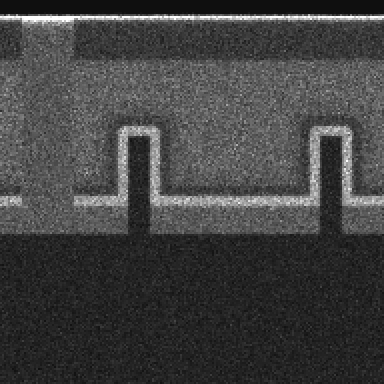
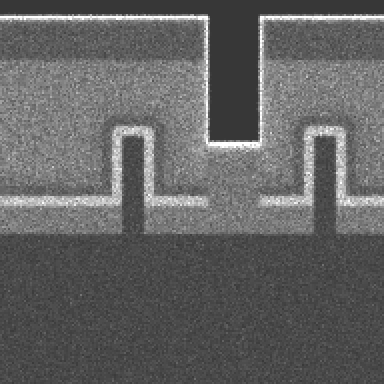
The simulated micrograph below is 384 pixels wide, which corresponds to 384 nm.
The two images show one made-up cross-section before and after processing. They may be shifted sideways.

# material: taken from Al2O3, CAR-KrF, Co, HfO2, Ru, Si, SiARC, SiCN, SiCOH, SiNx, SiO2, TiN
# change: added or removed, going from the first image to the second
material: SiO2
change: removed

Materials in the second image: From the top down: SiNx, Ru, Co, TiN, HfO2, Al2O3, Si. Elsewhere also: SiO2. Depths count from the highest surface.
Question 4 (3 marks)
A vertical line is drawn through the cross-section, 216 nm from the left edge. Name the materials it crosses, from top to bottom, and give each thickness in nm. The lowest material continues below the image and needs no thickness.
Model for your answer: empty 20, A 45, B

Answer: empty 126, SiO2 64, Al2O3 28, Si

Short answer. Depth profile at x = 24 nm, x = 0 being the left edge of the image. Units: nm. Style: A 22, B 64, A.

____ SiNx 44, Ru 114, Co 12, TiN 10, HfO2 10, Al2O3 28, Si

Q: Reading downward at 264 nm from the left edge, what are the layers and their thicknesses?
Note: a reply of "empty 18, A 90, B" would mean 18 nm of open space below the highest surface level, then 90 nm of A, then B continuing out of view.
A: SiNx 44, Ru 114, Co 12, TiN 10, HfO2 10, Al2O3 28, Si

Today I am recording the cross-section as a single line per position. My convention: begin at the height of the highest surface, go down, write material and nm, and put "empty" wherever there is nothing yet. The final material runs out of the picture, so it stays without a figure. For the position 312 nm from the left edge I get SiNx 44, Ru 44, Co 12, TiN 10, HfO2 80, Al2O3 28, Si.